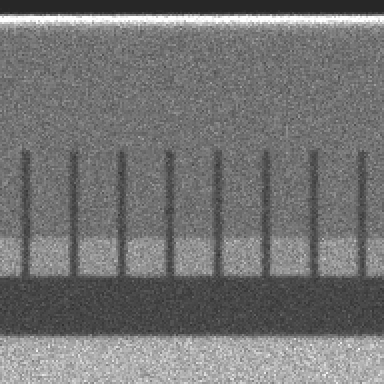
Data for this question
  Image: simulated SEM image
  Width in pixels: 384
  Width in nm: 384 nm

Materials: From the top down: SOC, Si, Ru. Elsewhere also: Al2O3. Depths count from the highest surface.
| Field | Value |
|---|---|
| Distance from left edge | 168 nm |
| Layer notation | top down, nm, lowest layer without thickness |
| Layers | SOC 134, Si 186, Ru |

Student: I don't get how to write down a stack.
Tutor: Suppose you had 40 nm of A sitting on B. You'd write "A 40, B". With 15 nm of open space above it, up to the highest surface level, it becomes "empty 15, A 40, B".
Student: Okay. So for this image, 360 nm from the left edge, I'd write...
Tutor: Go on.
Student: SOC 134, Si 186, Ru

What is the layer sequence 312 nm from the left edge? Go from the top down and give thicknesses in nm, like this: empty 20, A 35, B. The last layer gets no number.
SOC 134, Si 186, Ru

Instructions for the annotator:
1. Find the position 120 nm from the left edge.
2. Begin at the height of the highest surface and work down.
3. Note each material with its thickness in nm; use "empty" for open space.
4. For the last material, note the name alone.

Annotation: SOC 134, Si 186, Ru